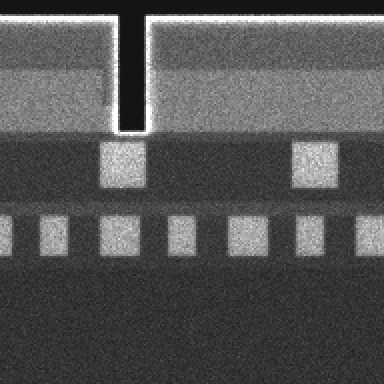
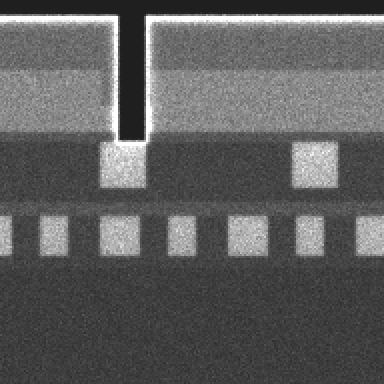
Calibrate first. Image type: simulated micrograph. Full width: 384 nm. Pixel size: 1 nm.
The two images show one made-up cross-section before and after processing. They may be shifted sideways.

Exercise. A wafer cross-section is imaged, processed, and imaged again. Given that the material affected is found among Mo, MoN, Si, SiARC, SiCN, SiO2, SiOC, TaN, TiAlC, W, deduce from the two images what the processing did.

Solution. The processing removed SiCN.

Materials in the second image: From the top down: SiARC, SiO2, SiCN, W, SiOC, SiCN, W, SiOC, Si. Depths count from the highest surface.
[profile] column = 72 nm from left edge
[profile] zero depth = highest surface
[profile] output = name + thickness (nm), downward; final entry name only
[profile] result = SiARC 54, SiO2 62, SiCN 10, SiOC 60, SiCN 14, SiOC 52, Si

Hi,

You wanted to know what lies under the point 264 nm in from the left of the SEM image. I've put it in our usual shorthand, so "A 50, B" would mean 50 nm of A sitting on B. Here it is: SiARC 54, SiO2 62, SiCN 10, SiOC 60, SiCN 14, W 40, SiOC 12, Si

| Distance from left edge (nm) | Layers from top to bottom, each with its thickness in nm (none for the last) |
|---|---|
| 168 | SiARC 54, SiO2 62, SiCN 10, SiOC 60, SiCN 14, W 40, SiOC 12, Si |